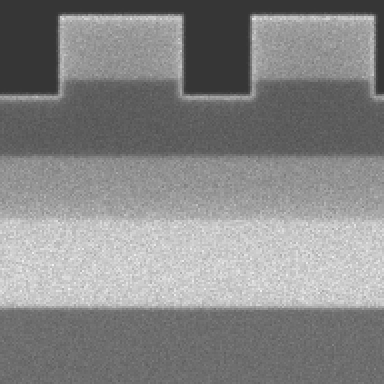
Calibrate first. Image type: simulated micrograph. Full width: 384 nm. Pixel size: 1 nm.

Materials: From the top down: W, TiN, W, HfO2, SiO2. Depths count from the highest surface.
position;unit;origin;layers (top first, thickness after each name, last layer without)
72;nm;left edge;W 64, TiN 76, W 64, HfO2 88, SiO2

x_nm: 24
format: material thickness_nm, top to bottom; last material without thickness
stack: empty 80, TiN 60, W 64, HfO2 88, SiO2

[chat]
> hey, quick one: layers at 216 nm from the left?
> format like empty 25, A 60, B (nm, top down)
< empty 80, TiN 60, W 64, HfO2 88, SiO2